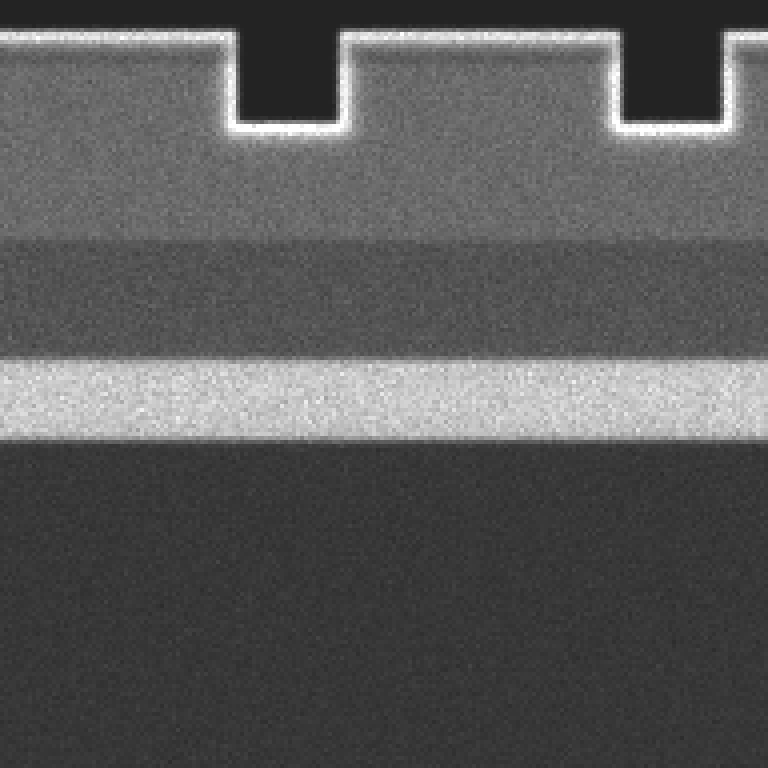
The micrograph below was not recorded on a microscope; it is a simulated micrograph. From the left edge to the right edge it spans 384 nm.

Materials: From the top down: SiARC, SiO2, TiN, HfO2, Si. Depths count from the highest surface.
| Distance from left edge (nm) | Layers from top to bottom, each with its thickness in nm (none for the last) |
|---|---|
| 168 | empty 46, SiO2 58, TiN 60, HfO2 40, Si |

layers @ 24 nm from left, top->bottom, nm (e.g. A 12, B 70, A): SiARC 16, SiO2 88, TiN 60, HfO2 40, Si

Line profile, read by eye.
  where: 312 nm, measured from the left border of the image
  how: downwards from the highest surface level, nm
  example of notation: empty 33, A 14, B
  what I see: empty 46, SiO2 58, TiN 60, HfO2 40, Si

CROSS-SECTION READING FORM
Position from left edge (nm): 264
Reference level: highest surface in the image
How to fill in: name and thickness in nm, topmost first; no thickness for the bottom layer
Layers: SiARC 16, SiO2 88, TiN 60, HfO2 40, Si